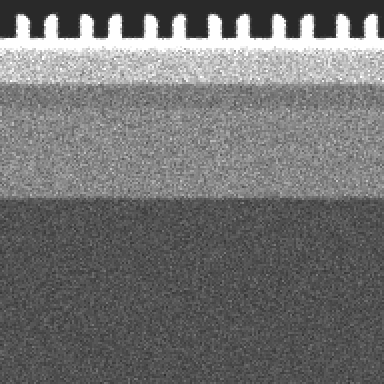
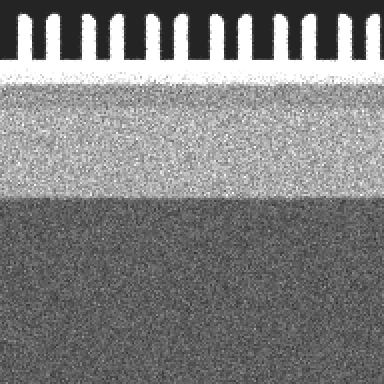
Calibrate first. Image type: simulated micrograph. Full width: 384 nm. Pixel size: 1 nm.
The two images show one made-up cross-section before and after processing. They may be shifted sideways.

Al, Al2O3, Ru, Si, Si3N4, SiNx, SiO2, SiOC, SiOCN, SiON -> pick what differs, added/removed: Al2O3 removed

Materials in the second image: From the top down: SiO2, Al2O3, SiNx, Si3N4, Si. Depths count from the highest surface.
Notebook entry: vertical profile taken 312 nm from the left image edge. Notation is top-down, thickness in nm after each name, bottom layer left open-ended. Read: SiO2 24, Al2O3 44, SiNx 24, Si3N4 90, Si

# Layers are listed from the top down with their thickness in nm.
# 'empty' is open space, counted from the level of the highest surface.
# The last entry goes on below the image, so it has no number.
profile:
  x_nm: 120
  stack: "SiO2 24, Al2O3 44, SiNx 24, Si3N4 90, Si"